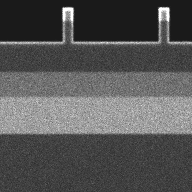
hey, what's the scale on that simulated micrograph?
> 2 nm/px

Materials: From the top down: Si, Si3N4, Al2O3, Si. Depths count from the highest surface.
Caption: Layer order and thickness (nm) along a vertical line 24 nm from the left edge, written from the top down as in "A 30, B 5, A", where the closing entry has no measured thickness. empty 68, Si 60, Si3N4 50, Al2O3 74, Si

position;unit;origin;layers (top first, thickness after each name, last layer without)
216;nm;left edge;empty 68, Si 60, Si3N4 50, Al2O3 74, Si